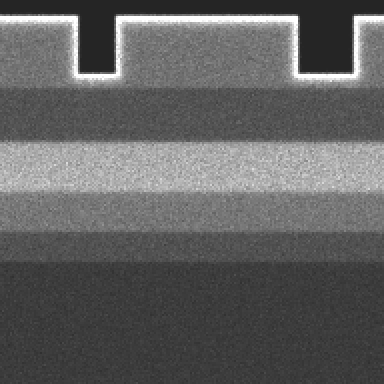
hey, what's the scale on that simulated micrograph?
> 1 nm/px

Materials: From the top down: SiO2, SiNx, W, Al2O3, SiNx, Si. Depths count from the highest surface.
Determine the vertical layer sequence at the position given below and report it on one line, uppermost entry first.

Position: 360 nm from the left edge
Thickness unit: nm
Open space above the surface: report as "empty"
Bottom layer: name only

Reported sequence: SiO2 72, SiNx 54, W 50, Al2O3 40, SiNx 30, Si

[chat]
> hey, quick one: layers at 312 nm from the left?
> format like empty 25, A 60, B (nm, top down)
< empty 58, SiO2 14, SiNx 54, W 50, Al2O3 40, SiNx 30, Si